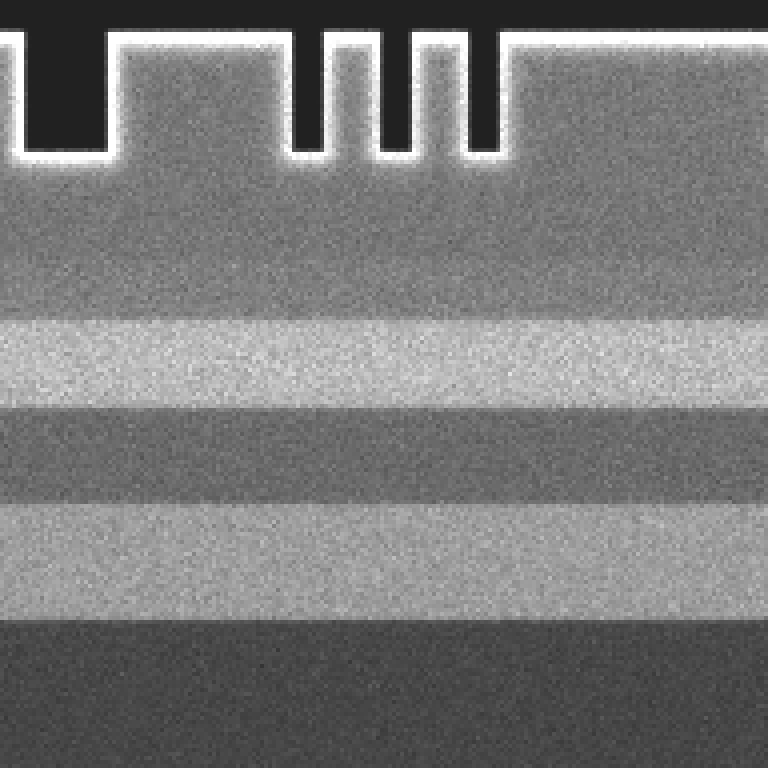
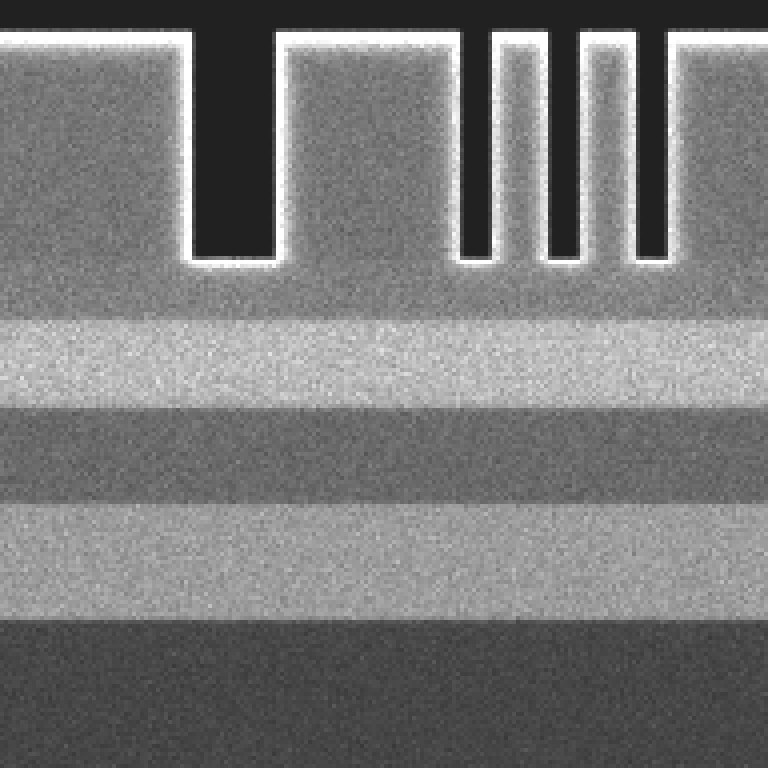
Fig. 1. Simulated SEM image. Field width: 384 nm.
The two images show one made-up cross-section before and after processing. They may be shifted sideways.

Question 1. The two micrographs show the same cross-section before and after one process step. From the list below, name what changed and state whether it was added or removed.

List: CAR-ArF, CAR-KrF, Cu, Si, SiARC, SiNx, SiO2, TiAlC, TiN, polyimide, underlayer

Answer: underlayer, removed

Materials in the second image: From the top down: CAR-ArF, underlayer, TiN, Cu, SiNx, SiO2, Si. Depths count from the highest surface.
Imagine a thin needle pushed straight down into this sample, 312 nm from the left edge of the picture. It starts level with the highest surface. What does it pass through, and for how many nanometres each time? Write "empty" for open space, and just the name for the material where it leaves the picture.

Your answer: CAR-ArF 60, underlayer 54, TiN 30, Cu 44, SiNx 48, SiO2 58, Si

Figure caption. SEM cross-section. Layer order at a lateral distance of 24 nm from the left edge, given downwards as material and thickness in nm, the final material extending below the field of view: CAR-ArF 60, underlayer 54, TiN 30, Cu 44, SiNx 48, SiO2 58, Si